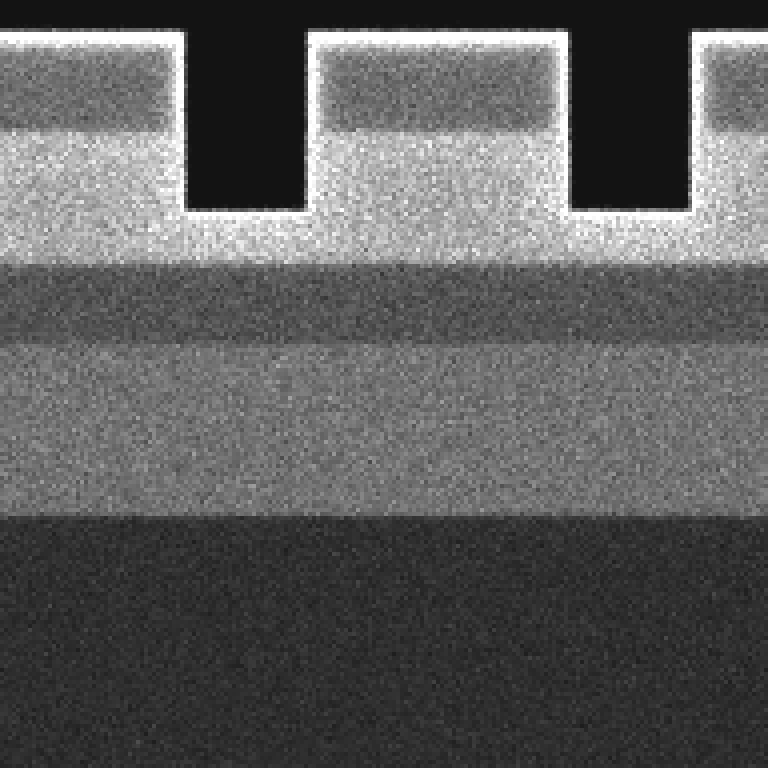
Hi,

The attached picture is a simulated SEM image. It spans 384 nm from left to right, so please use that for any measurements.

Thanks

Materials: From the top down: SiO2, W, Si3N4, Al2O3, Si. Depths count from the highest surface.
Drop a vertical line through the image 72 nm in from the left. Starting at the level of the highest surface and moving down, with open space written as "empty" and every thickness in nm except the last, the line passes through SiO2 50, W 66, Si3N4 40, Al2O3 86, Si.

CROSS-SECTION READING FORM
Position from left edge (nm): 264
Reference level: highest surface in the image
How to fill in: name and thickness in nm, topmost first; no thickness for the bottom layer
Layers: SiO2 50, W 66, Si3N4 40, Al2O3 86, Si